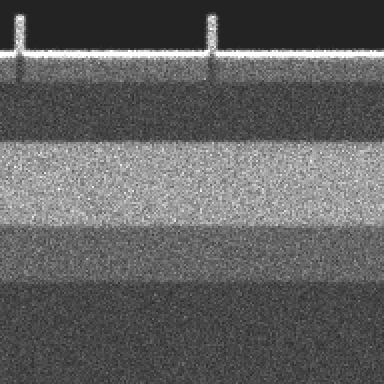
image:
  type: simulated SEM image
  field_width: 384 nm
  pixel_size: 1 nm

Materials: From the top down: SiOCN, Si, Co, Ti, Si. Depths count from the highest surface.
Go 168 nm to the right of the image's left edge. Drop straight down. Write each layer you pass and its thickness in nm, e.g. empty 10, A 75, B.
empty 36, SiOCN 30, Si 60, Co 84, Ti 56, Si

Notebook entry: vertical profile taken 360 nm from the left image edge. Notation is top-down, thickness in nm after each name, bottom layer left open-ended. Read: empty 36, SiOCN 30, Si 60, Co 84, Ti 56, Si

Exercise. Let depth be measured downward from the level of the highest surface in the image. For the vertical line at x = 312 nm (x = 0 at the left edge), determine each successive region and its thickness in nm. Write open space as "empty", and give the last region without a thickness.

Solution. empty 36, SiOCN 30, Si 60, Co 84, Ti 56, Si